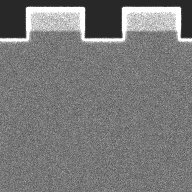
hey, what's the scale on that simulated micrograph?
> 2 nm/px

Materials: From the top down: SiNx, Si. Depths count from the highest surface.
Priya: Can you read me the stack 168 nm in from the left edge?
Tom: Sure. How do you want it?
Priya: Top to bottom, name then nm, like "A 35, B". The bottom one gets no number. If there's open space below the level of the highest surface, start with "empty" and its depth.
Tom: empty 62, Si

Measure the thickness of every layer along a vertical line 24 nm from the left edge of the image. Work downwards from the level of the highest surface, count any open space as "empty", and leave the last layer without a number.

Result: empty 62, Si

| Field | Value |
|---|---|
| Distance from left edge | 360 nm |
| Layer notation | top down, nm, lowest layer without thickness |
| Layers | empty 62, Si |